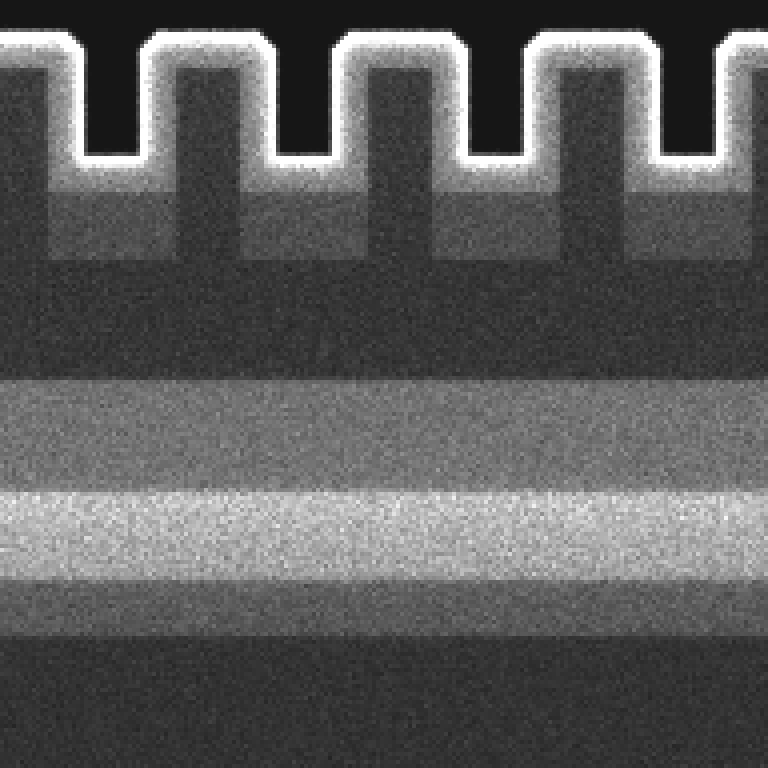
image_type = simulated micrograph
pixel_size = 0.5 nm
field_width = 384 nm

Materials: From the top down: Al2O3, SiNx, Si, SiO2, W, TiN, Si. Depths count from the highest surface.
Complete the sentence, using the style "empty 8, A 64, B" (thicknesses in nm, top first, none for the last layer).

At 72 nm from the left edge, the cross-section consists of empty 6, Al2O3 74, SiNx 34, Si 60, SiO2 56, W 44, TiN 28, Si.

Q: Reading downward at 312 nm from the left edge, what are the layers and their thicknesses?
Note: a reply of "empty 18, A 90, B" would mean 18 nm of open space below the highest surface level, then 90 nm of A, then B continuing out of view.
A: Al2O3 80, SiNx 34, Si 60, SiO2 56, W 44, TiN 28, Si